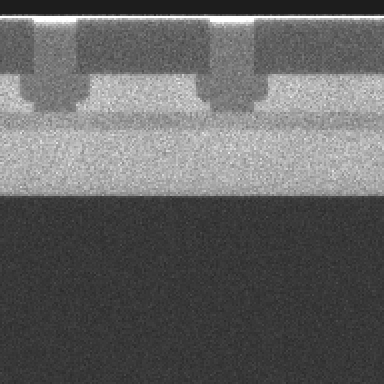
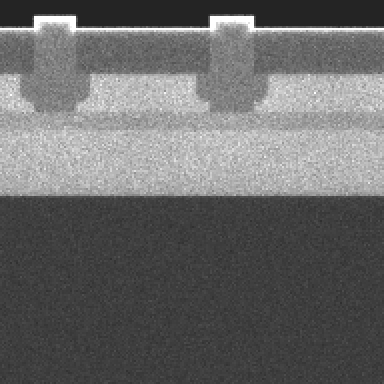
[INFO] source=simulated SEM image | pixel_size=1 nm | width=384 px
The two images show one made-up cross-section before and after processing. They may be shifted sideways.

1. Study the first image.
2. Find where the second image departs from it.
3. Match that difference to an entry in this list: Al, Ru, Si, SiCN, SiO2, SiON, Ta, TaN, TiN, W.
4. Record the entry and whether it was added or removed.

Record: TiN / removed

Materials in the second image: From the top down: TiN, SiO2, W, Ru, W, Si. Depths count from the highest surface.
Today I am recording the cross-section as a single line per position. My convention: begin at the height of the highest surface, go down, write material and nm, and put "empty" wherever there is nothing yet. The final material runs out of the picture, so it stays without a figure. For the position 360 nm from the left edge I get empty 12, TiN 46, W 38, Ru 18, W 66, Si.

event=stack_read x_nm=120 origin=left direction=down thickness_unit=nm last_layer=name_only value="empty 12, TiN 46, W 38, Ru 18, W 66, Si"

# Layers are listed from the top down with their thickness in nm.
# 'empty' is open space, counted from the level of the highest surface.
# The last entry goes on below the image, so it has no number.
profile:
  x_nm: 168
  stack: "empty 12, TiN 46, W 38, Ru 18, W 66, Si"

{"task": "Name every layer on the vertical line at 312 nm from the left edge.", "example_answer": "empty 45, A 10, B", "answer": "empty 12, TiN 46, W 38, Ru 18, W 66, Si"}